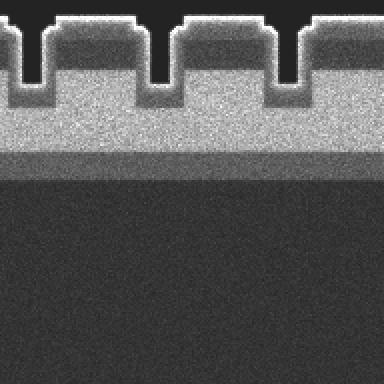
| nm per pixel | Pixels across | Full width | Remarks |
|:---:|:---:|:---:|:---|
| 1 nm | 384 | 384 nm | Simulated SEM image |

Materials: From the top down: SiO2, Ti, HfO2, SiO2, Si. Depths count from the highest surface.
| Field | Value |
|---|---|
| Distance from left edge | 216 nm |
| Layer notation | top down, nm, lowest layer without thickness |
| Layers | SiO2 24, Ti 30, HfO2 82, SiO2 28, Si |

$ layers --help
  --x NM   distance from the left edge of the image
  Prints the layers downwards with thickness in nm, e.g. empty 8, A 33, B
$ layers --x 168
empty 68, SiO2 24, HfO2 44, SiO2 28, Si